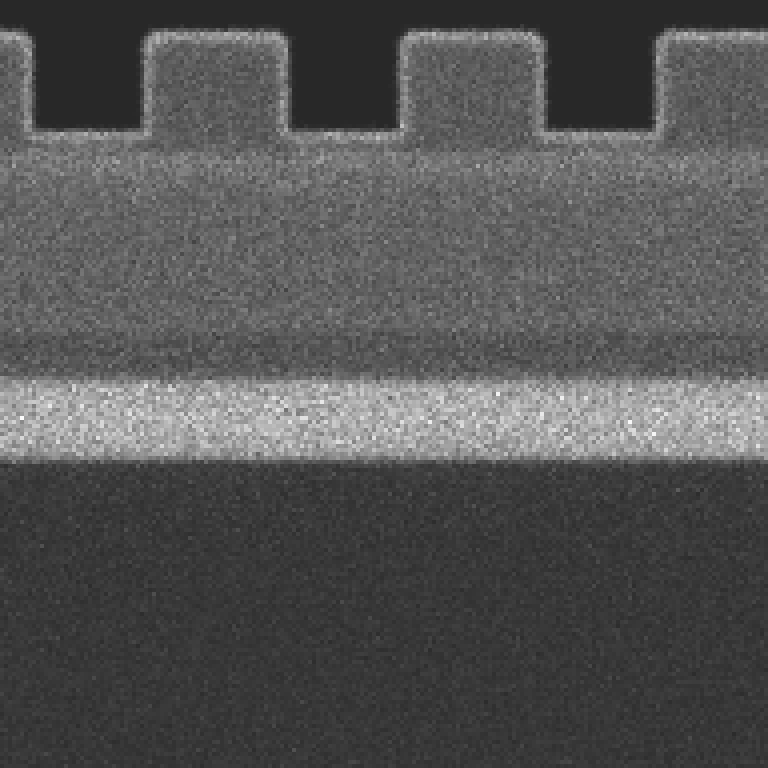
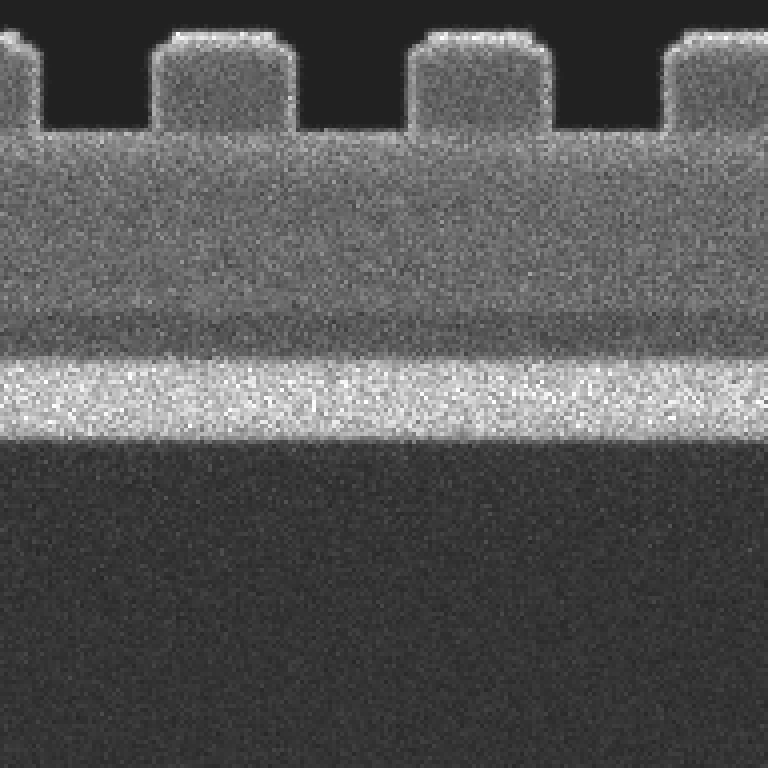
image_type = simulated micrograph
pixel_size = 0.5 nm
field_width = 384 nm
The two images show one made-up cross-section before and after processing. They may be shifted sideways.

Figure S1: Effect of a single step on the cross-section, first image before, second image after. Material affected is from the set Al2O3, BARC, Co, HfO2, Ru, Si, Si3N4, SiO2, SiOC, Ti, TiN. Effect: removed Si3N4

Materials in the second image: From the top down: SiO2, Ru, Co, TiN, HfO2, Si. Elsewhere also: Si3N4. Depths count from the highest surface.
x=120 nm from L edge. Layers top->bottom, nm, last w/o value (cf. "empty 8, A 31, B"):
SiO2 50, Ru 64, Co 26, TiN 24, HfO2 40, Si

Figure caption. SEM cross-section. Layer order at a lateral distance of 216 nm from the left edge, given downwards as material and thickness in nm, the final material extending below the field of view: SiO2 50, Ru 64, Co 26, TiN 24, HfO2 40, Si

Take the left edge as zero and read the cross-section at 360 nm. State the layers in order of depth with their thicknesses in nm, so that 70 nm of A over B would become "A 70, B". SiO2 50, Ru 64, Co 26, TiN 24, HfO2 40, Si